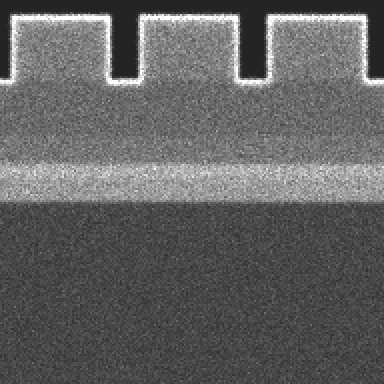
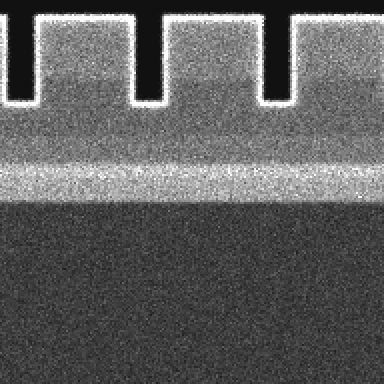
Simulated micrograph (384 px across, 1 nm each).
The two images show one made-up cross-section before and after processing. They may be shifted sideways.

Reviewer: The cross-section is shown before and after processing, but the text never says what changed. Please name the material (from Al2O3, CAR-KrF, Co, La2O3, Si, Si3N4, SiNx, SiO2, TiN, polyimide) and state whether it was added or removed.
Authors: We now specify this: SiNx, removed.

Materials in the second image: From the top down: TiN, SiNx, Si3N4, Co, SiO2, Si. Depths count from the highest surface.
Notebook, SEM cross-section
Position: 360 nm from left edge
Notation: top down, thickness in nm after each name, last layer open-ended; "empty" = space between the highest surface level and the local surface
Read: TiN 64, SiNx 56, Si3N4 28, Co 14, SiO2 24, Si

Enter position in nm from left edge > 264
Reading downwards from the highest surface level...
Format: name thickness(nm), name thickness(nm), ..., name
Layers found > empty 86, SiNx 34, Si3N4 28, Co 14, SiO2 24, Si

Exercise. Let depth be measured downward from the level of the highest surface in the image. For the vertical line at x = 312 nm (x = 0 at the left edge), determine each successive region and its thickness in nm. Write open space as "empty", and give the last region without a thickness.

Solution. TiN 64, SiNx 56, Si3N4 28, Co 14, SiO2 24, Si